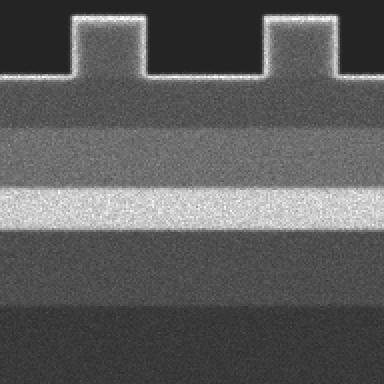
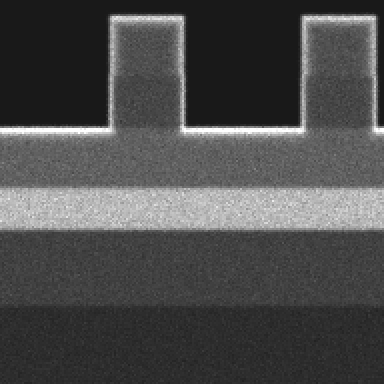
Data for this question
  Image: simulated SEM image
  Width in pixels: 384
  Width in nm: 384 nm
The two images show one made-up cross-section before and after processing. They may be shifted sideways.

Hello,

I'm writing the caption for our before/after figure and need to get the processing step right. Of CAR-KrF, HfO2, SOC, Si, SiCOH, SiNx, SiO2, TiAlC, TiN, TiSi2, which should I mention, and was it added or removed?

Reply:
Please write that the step removed TiN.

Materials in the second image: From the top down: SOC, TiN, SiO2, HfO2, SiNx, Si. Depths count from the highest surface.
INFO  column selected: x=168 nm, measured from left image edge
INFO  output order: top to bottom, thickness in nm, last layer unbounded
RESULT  SOC 60, TiN 52, SiO2 60, HfO2 42, SiNx 76, Si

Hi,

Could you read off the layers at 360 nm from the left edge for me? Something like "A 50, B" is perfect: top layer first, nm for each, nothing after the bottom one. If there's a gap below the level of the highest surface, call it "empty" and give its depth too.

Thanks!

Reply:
SOC 60, TiN 52, SiO2 60, HfO2 42, SiNx 76, Si